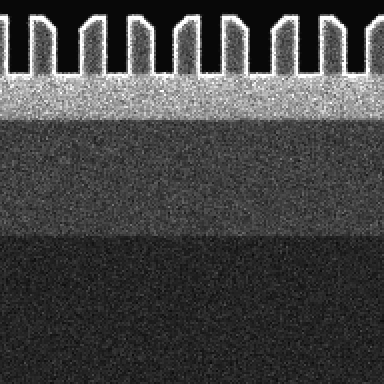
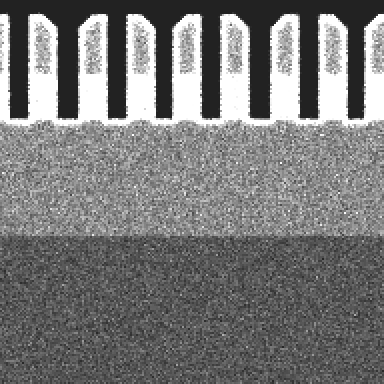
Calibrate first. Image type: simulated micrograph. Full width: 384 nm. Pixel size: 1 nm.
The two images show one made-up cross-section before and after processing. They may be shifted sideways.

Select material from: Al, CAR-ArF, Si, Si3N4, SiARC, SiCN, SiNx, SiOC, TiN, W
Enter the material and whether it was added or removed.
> W / removed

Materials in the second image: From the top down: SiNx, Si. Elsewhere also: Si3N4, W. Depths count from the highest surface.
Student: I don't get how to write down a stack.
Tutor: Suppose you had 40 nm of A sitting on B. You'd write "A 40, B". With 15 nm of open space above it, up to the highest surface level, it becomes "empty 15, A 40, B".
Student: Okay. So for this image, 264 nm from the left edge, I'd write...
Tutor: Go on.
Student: empty 104, SiNx 116, Si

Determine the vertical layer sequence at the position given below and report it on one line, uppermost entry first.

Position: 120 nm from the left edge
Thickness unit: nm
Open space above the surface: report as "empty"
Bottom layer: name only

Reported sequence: empty 104, SiNx 116, Si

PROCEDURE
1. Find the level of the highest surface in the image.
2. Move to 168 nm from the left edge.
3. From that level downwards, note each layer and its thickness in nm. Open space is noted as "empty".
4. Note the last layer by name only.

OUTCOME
empty 104, SiNx 116, Si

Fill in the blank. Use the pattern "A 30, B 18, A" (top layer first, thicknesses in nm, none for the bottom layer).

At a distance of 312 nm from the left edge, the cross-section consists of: empty 104, SiNx 116, Si